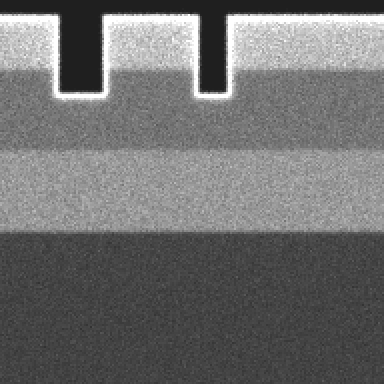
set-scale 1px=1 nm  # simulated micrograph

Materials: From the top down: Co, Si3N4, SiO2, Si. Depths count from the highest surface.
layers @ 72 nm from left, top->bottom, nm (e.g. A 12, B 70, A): empty 78, Si3N4 56, SiO2 82, Si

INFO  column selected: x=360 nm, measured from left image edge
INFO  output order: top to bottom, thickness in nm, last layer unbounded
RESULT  Co 54, Si3N4 80, SiO2 82, Si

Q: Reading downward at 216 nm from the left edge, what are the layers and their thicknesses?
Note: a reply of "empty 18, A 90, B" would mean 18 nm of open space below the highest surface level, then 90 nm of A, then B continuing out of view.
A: empty 78, Si3N4 56, SiO2 82, Si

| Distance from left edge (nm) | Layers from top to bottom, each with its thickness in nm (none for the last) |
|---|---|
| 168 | Co 54, Si3N4 80, SiO2 82, Si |